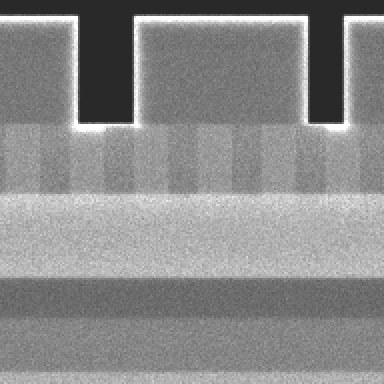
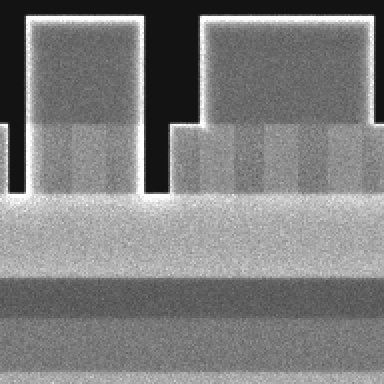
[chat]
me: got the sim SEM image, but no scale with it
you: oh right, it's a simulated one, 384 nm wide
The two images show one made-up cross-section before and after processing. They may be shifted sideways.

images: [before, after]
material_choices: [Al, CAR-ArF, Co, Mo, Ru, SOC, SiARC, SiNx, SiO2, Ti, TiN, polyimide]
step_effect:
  removed: SiO2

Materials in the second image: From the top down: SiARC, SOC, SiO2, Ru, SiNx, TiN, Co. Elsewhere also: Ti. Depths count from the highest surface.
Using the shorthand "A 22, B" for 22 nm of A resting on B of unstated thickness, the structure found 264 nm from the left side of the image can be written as SiARC 34, SOC 74, SiO2 70, Ru 84, SiNx 40, TiN 54, Co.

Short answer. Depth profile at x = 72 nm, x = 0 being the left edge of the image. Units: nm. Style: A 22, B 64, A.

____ SiARC 34, SOC 74, SiO2 70, Ru 84, SiNx 40, TiN 54, Co